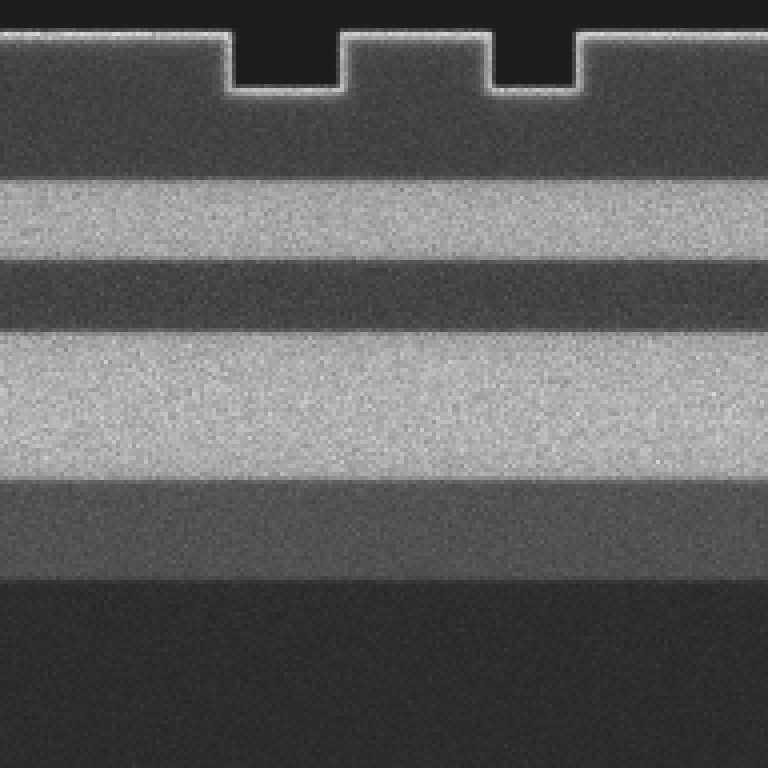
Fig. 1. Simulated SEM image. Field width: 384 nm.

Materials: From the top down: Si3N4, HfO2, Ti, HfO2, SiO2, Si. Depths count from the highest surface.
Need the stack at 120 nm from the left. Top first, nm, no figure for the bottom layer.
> empty 28, Si3N4 46, HfO2 40, Ti 36, HfO2 74, SiO2 50, Si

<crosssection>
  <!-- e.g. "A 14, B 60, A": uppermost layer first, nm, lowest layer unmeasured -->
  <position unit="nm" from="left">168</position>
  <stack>empty 28, Si3N4 46, HfO2 40, Ti 36, HfO2 74, SiO2 50, Si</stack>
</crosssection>